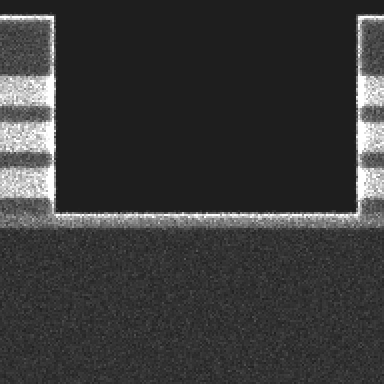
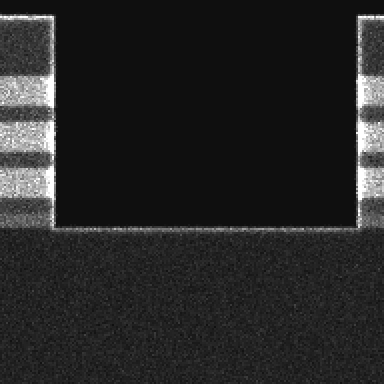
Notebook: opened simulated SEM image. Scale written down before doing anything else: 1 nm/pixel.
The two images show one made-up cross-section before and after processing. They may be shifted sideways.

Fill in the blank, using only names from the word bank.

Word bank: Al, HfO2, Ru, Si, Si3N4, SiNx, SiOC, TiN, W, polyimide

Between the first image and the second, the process removed Ru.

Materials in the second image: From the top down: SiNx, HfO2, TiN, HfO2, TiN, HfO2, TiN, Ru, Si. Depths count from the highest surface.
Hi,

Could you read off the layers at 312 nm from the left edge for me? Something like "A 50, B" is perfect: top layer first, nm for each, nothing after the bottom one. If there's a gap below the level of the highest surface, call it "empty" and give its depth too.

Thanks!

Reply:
empty 212, Si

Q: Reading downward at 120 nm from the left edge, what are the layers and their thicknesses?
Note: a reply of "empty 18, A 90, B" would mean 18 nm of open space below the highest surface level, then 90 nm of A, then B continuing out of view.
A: empty 212, Si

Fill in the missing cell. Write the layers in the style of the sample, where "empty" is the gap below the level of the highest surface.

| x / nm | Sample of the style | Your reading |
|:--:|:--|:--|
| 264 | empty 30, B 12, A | empty 212, Si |